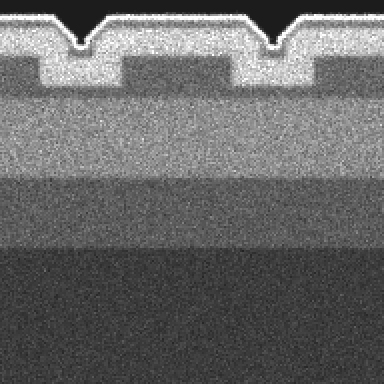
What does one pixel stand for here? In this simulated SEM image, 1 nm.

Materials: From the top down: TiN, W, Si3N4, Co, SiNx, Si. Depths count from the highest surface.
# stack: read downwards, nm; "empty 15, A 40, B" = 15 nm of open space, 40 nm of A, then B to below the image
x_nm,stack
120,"TiN 12, W 58, Si3N4 12, Co 80, SiNx 70, Si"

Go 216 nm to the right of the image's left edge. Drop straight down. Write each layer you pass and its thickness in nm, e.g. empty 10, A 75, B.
TiN 12, W 28, Si3N4 42, Co 80, SiNx 70, Si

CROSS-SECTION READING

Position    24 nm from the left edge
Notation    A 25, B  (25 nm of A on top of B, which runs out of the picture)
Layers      TiN 12, W 28, Si3N4 42, Co 80, SiNx 70, Si